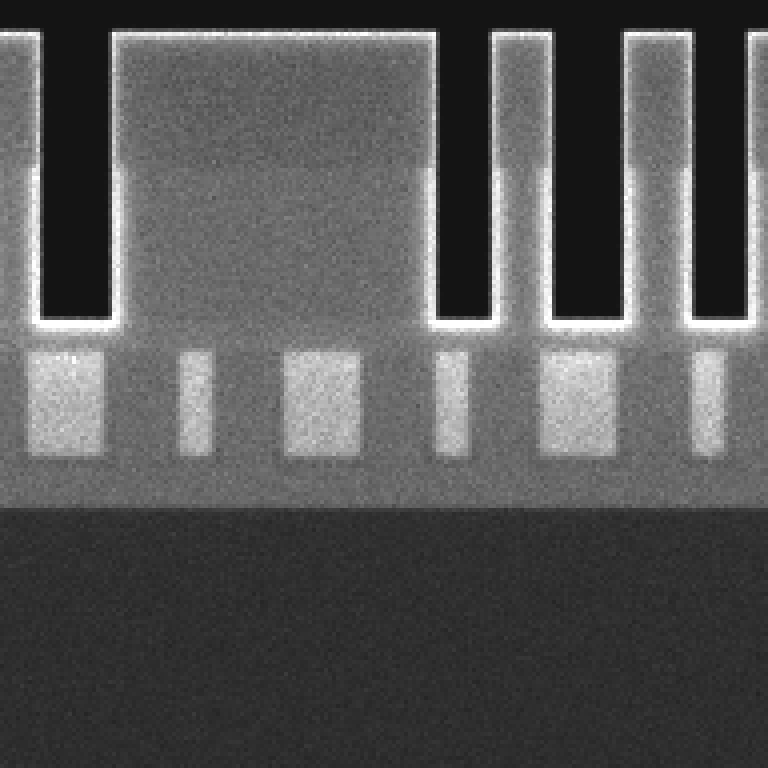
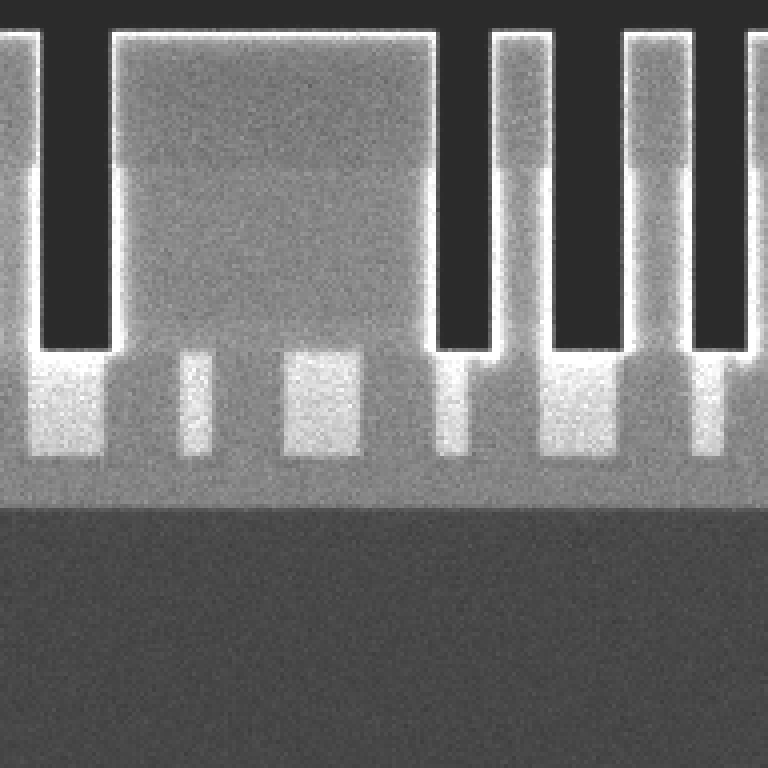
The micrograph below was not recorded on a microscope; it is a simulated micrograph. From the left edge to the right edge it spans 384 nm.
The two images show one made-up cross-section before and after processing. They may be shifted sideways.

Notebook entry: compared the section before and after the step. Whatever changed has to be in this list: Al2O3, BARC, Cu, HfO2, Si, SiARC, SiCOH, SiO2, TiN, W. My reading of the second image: Al2O3 removed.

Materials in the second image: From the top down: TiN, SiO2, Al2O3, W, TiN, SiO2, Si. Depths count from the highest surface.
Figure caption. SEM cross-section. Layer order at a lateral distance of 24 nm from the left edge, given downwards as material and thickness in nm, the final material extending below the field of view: empty 160, W 52, TiN 6, SiO2 20, Si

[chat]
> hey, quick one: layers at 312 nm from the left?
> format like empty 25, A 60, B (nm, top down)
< TiN 68, SiO2 76, Al2O3 16, TiN 58, SiO2 20, Si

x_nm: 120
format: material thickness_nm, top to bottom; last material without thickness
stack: TiN 68, SiO2 76, Al2O3 16, SiO2 78, Si